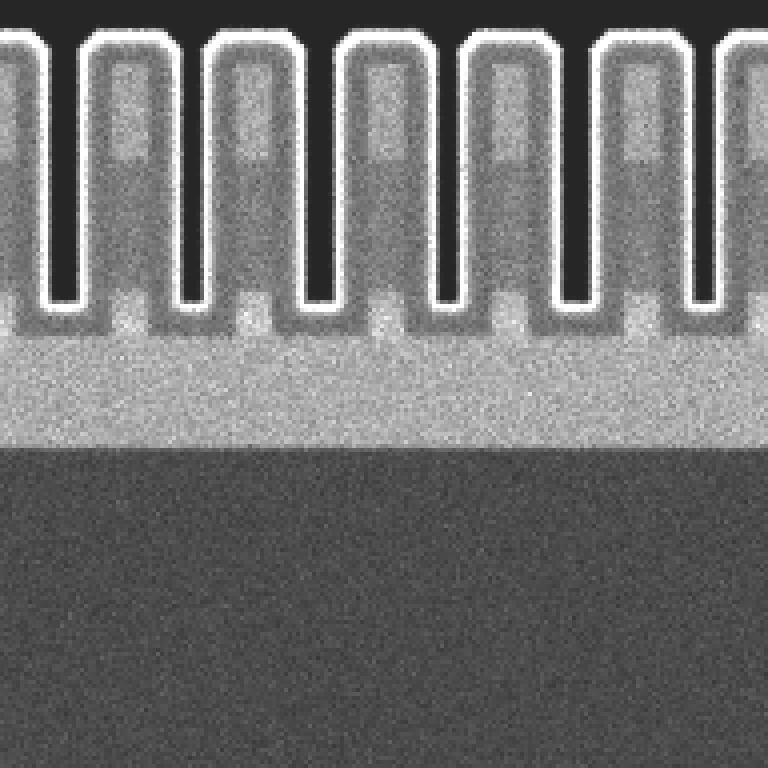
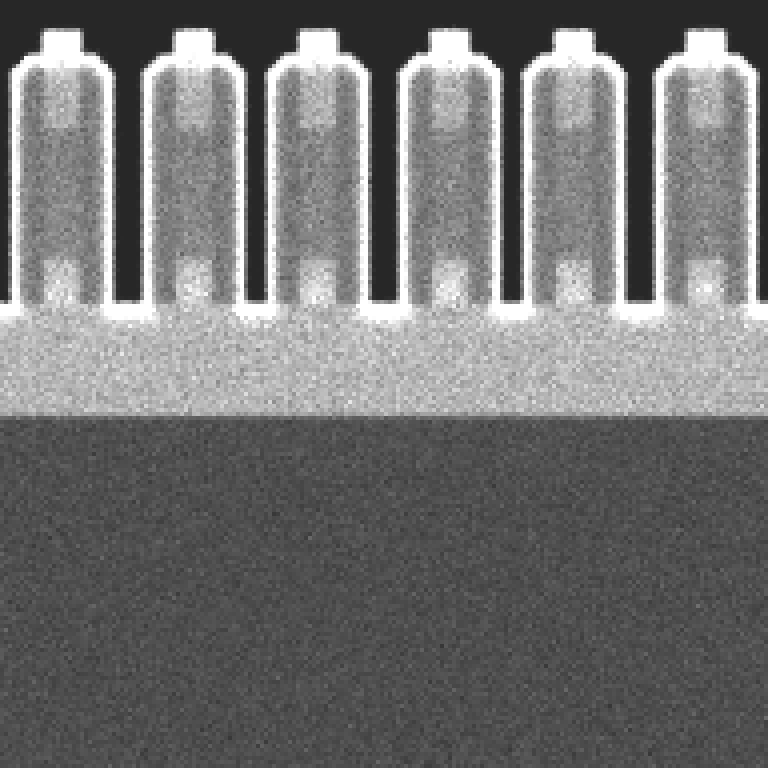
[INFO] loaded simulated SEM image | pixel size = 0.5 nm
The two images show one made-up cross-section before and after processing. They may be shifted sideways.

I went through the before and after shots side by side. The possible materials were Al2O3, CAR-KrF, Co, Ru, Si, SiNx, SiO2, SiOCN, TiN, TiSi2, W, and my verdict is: removed, SiNx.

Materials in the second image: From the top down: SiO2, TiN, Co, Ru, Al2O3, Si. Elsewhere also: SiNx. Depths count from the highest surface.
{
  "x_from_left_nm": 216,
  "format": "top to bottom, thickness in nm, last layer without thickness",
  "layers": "SiO2 48, TiN 66, Co 12, Ru 10, Al2O3 56, Si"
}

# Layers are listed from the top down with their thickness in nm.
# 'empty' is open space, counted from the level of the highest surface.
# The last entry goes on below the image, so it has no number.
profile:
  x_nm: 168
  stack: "empty 12, SiNx 124, Al2O3 56, Si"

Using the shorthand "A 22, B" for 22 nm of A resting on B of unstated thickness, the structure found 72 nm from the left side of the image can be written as empty 20, SiNx 116, Al2O3 56, Si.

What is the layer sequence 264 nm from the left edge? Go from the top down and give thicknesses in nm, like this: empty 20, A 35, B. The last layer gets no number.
empty 18, SiNx 118, Al2O3 56, Si